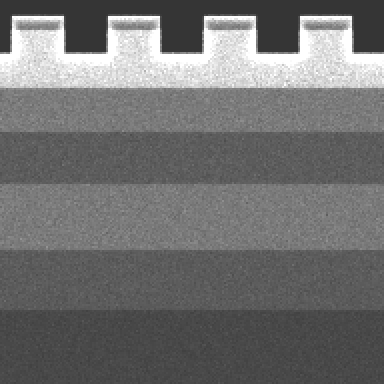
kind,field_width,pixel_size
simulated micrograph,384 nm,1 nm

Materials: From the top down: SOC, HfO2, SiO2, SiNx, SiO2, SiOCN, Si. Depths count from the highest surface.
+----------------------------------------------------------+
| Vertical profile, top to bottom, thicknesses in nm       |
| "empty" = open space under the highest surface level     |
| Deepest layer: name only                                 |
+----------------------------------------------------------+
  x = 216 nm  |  SOC 14, HfO2 58, SiO2 44, SiNx 52, SiO2 66, SiOCN 60, Si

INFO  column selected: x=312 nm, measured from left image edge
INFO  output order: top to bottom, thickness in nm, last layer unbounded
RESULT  SOC 14, HfO2 58, SiO2 44, SiNx 52, SiO2 66, SiOCN 60, Si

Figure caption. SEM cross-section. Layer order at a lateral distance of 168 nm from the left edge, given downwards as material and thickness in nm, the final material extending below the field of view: empty 38, HfO2 34, SiO2 44, SiNx 52, SiO2 66, SiOCN 60, Si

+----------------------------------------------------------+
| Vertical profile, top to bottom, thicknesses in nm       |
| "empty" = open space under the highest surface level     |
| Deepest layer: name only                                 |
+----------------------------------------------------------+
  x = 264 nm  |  empty 38, HfO2 34, SiO2 44, SiNx 52, SiO2 66, SiOCN 60, Si